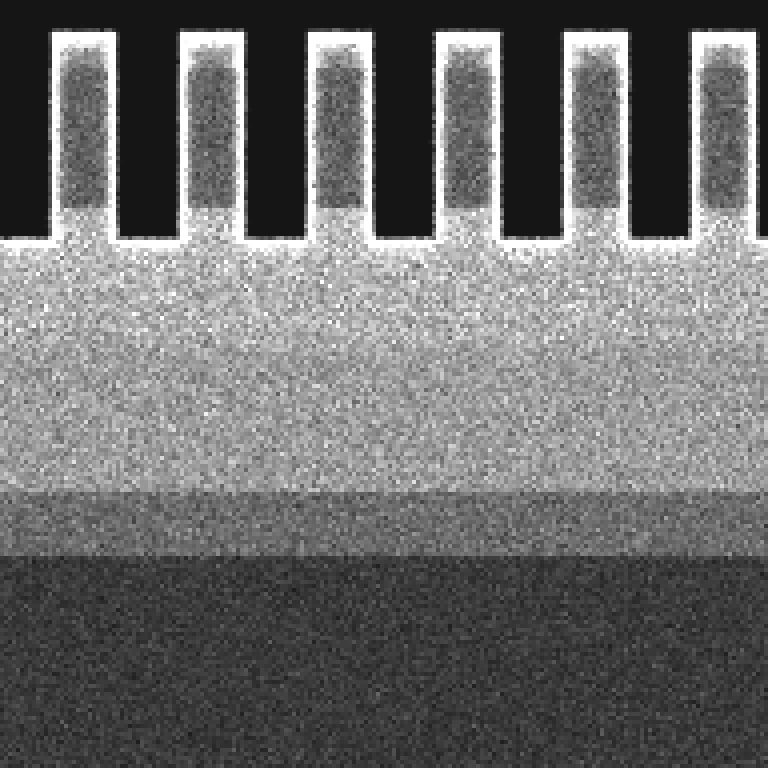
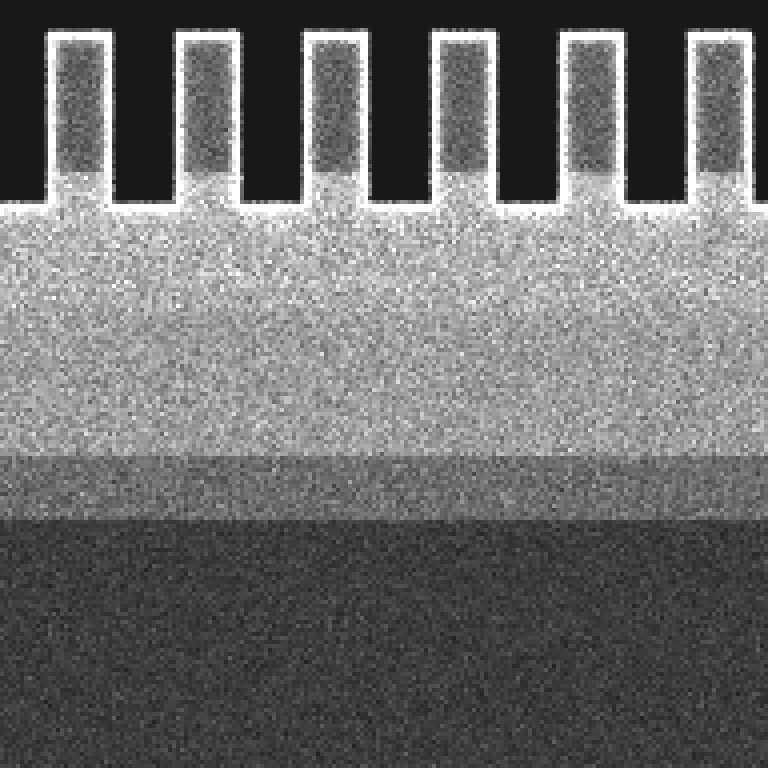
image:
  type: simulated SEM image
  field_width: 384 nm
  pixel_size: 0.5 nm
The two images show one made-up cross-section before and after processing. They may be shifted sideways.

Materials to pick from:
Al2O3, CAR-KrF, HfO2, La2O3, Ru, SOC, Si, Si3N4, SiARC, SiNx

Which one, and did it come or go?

SOC - removed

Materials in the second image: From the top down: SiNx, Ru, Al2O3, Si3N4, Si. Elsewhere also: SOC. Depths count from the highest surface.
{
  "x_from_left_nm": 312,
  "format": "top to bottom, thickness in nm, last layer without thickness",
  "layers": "empty 86, Ru 54, Al2O3 72, Si3N4 32, Si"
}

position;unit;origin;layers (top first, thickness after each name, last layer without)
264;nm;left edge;empty 86, Ru 54, Al2O3 72, Si3N4 32, Si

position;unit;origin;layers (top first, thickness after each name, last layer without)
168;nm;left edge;SiNx 70, Ru 70, Al2O3 72, Si3N4 32, Si